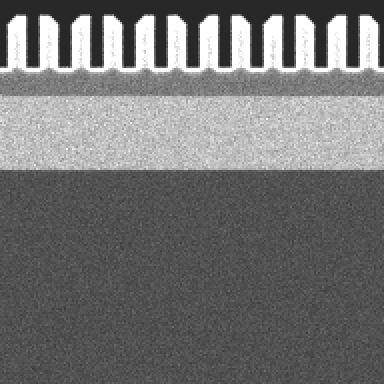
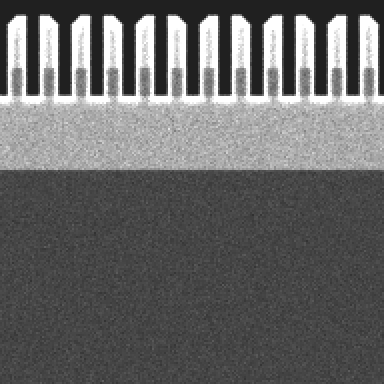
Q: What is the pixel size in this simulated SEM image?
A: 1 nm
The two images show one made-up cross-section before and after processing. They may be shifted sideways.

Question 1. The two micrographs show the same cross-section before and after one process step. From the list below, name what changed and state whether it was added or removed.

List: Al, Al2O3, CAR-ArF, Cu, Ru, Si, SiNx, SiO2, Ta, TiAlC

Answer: SiNx, removed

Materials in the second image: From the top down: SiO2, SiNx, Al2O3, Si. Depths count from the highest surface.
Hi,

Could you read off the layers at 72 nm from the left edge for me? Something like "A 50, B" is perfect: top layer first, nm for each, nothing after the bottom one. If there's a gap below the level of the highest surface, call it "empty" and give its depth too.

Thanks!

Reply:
empty 8, SiO2 44, SiNx 28, Al2O3 74, Si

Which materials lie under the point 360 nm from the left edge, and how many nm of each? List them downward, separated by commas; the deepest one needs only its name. SiO2 52, SiNx 28, Al2O3 74, Si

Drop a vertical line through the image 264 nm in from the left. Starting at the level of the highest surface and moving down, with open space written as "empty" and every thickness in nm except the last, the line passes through empty 8, SiO2 44, SiNx 28, Al2O3 74, Si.